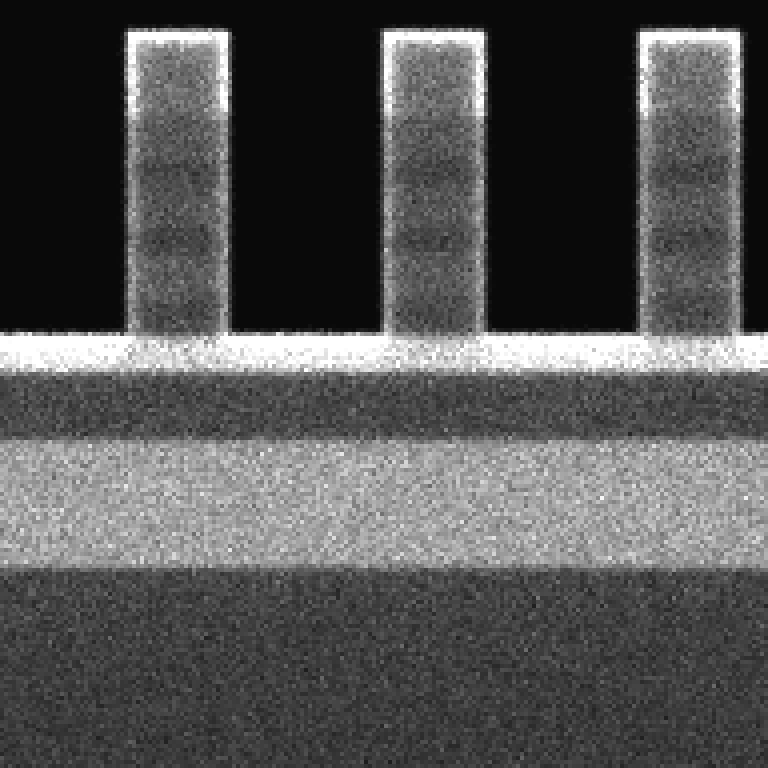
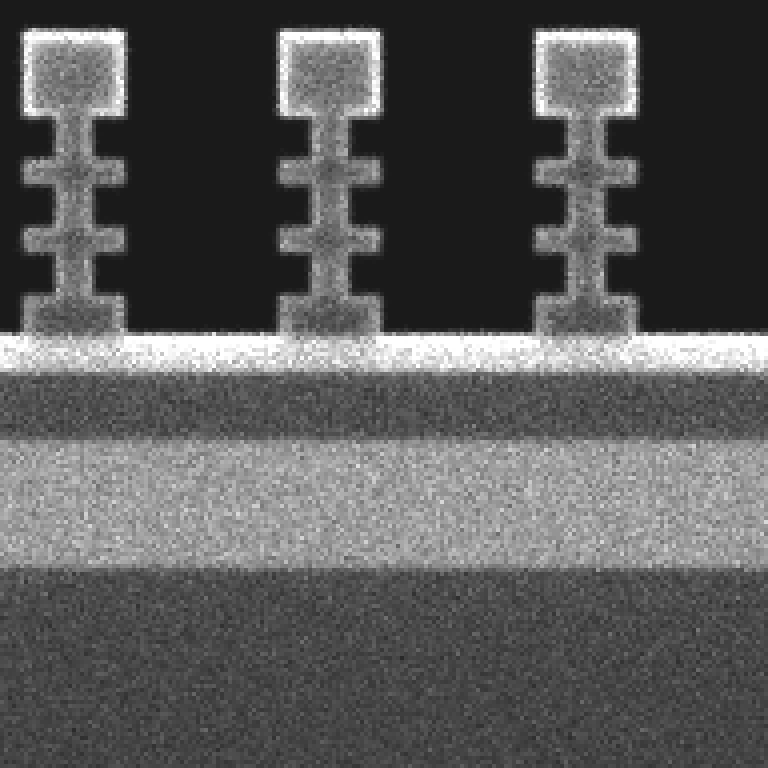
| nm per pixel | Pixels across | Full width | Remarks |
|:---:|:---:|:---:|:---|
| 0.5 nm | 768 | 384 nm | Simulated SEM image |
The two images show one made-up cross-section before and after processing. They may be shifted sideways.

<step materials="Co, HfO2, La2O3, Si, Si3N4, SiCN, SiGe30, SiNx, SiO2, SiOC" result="removed SiGe30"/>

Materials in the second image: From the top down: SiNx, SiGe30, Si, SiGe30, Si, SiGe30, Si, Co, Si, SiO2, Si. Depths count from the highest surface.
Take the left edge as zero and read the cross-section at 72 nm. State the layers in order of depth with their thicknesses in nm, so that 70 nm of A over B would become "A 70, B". empty 152, Co 18, Si 34, SiO2 64, Si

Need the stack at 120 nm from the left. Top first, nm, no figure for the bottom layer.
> empty 152, Co 18, Si 34, SiO2 64, Si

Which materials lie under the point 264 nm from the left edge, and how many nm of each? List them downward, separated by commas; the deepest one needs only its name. empty 152, Co 18, Si 34, SiO2 64, Si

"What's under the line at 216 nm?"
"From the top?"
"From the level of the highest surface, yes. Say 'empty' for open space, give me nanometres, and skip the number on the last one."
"empty 152, Co 18, Si 34, SiO2 64, Si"